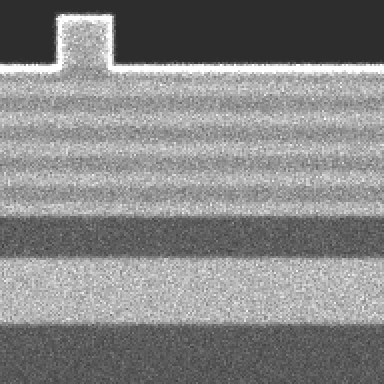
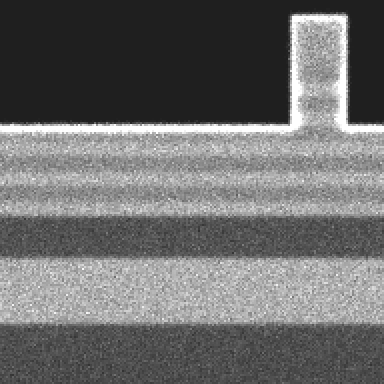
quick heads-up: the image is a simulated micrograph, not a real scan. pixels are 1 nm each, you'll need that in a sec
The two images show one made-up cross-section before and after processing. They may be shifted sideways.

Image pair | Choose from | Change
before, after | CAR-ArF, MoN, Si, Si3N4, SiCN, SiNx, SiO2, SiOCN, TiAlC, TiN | Si3N4 and SiO2 (removed)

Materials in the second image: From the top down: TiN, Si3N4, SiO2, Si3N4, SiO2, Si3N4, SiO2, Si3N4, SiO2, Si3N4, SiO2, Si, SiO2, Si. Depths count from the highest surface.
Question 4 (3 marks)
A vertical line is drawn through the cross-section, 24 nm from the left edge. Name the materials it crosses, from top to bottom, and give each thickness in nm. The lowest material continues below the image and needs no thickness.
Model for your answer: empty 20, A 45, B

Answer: empty 110, Si3N4 16, SiO2 14, Si3N4 16, SiO2 14, Si3N4 16, SiO2 14, Si 42, SiO2 66, Si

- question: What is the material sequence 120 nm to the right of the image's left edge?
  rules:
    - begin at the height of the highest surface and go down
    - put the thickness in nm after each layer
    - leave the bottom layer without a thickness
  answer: empty 110, Si3N4 16, SiO2 14, Si3N4 16, SiO2 14, Si3N4 16, SiO2 14, Si 42, SiO2 66, Si